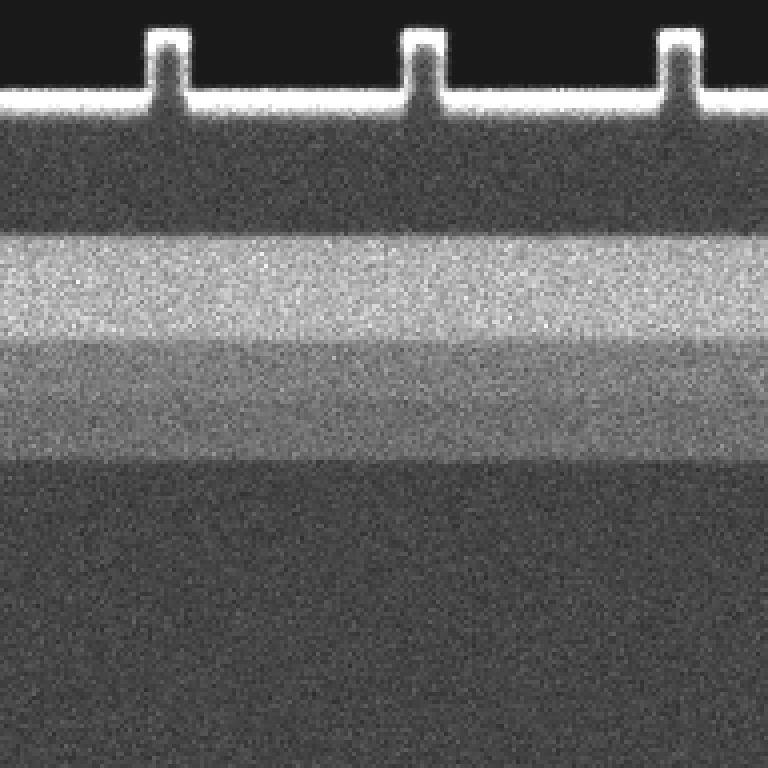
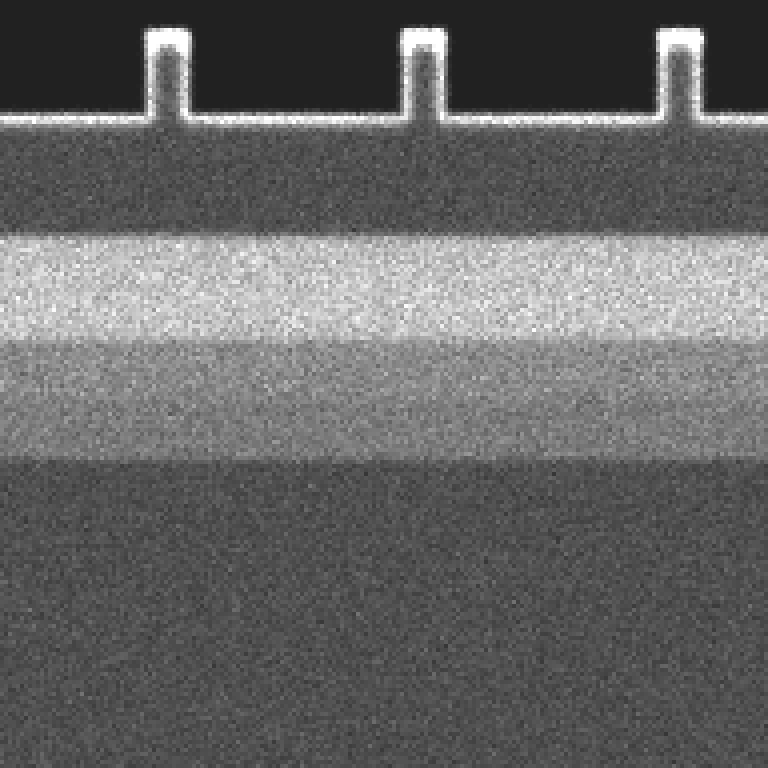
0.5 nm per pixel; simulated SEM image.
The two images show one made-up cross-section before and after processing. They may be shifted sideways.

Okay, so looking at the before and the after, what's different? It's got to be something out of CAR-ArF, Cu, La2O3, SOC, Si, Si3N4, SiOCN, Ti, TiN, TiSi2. SOC, removed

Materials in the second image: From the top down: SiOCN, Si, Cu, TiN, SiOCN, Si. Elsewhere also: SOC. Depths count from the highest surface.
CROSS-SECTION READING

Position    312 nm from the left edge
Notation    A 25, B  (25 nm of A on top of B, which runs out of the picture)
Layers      empty 42, Si 60, Cu 52, TiN 30, SiOCN 30, Si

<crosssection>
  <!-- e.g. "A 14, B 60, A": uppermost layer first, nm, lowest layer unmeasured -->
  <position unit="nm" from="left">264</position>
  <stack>empty 42, Si 60, Cu 52, TiN 30, SiOCN 30, Si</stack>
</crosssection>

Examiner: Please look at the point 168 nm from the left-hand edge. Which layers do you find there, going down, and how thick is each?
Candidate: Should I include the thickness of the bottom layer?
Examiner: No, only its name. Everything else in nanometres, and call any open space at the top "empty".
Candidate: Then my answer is empty 42, Si 60, Cu 52, TiN 30, SiOCN 30, Si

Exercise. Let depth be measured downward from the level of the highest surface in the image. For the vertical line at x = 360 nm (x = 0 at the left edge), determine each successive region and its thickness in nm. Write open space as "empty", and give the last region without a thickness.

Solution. empty 42, Si 60, Cu 52, TiN 30, SiOCN 30, Si